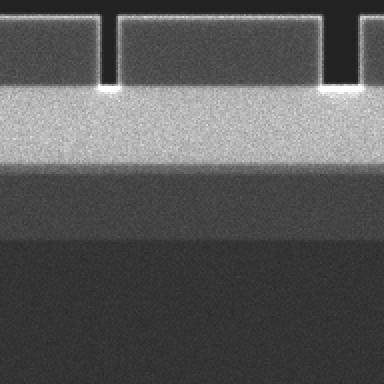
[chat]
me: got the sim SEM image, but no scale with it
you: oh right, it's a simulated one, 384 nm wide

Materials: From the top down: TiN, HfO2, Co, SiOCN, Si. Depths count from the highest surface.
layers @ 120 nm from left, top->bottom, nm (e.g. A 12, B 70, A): TiN 70, HfO2 78, Co 10, SiOCN 66, Si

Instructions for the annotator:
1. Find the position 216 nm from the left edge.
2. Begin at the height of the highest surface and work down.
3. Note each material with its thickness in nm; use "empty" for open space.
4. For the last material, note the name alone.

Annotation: TiN 70, HfO2 78, Co 10, SiOCN 66, Si